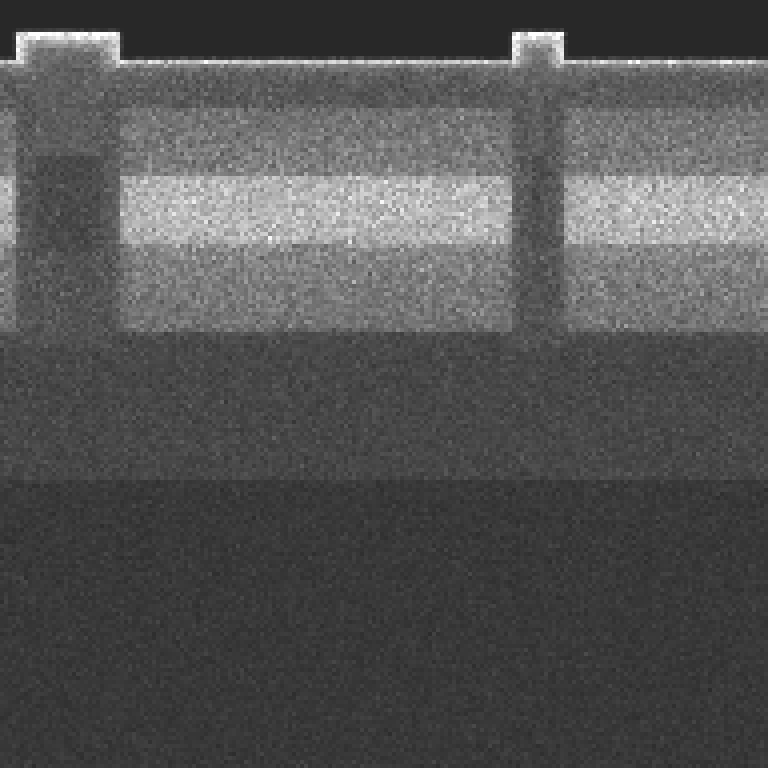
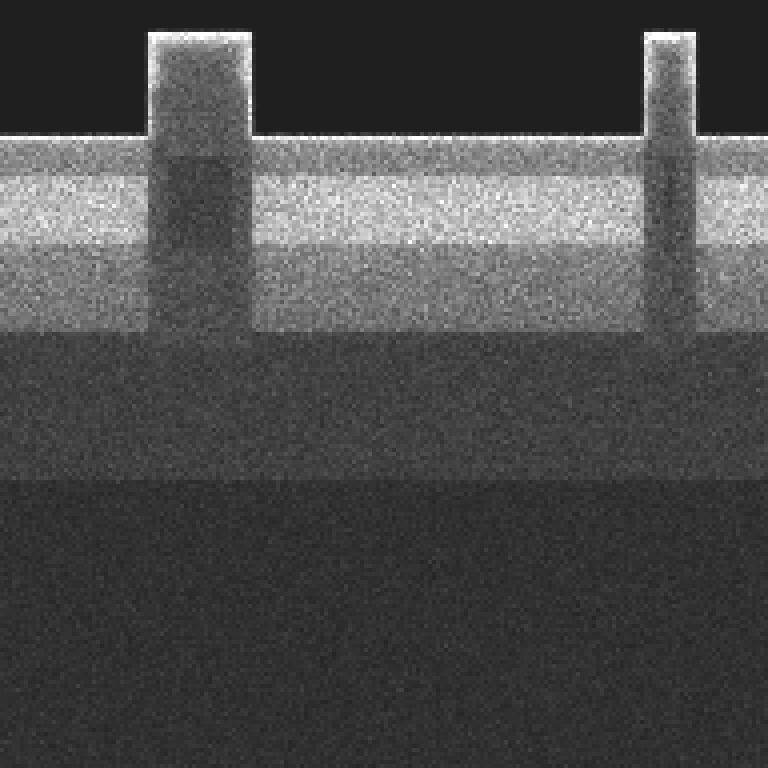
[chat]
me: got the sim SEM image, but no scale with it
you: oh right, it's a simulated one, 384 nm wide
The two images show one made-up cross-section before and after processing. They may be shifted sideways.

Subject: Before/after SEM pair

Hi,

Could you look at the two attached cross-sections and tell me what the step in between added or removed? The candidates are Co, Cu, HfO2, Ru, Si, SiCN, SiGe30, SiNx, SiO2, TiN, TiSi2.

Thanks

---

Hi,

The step removed Co and TiN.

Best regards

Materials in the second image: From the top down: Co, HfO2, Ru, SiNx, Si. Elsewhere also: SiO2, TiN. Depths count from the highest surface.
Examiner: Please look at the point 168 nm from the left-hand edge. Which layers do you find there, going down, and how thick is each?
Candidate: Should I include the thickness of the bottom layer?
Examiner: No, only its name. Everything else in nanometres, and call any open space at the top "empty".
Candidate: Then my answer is empty 52, Co 20, HfO2 34, Ru 44, SiNx 74, Si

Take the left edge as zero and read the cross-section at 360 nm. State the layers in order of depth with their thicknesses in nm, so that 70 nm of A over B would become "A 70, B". empty 52, Co 20, HfO2 34, Ru 44, SiNx 74, Si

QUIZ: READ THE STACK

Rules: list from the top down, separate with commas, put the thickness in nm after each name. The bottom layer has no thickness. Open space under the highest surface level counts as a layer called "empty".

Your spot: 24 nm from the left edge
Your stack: empty 52, Co 20, HfO2 34, Ru 44, SiNx 74, Si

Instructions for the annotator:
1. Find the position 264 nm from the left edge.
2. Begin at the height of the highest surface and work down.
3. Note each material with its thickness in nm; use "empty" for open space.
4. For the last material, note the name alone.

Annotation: empty 52, Co 20, HfO2 34, Ru 44, SiNx 74, Si